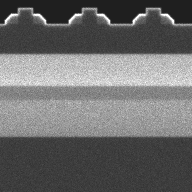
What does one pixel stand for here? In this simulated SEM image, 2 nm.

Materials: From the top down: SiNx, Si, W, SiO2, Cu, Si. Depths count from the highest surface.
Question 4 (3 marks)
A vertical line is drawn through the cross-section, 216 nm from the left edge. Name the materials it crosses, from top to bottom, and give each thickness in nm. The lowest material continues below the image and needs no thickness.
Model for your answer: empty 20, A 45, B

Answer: empty 22, SiNx 10, Si 60, W 64, SiO2 28, Cu 74, Si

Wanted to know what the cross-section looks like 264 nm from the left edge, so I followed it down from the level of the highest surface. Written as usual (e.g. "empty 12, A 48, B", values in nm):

empty 32, Si 60, W 64, SiO2 28, Cu 74, Si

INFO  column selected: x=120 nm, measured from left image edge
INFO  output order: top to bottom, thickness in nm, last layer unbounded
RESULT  empty 32, Si 60, W 64, SiO2 28, Cu 74, Si